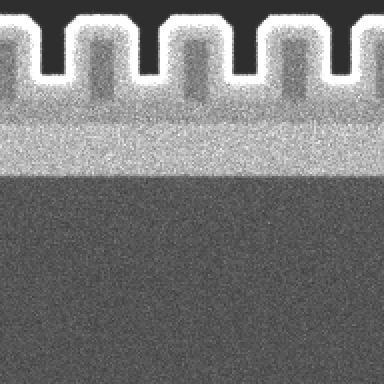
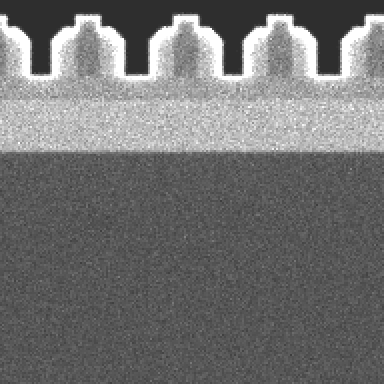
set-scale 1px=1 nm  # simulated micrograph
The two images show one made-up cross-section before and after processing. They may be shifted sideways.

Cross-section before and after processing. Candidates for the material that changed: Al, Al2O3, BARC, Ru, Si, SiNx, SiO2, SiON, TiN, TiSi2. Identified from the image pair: SiO2 (removed).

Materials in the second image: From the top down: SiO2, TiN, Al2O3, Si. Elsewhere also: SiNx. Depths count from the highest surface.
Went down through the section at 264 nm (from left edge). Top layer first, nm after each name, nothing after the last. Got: empty 12, SiO2 48, TiN 24, Al2O3 52, Si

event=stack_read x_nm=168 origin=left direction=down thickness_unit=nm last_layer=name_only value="empty 12, SiO2 48, TiN 24, Al2O3 52, Si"